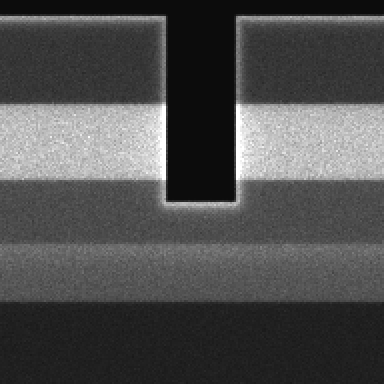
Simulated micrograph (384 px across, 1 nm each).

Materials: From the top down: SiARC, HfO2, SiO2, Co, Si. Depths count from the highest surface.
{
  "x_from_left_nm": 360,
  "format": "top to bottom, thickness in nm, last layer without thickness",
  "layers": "SiARC 88, HfO2 76, SiO2 64, Co 58, Si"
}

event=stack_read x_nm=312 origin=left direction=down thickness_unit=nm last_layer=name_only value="SiARC 88, HfO2 76, SiO2 64, Co 58, Si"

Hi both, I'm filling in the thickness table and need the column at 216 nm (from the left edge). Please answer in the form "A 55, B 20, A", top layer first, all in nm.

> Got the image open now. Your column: empty 186, SiO2 42, Co 58, Si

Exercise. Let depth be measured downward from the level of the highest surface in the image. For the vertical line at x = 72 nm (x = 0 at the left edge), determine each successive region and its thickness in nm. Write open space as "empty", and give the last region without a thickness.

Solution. SiARC 88, HfO2 76, SiO2 64, Co 58, Si